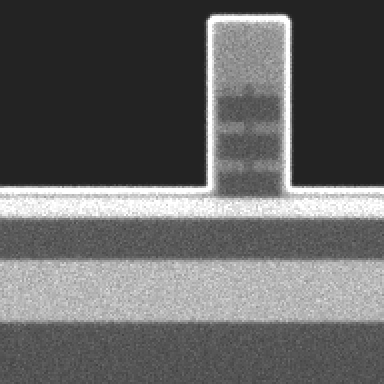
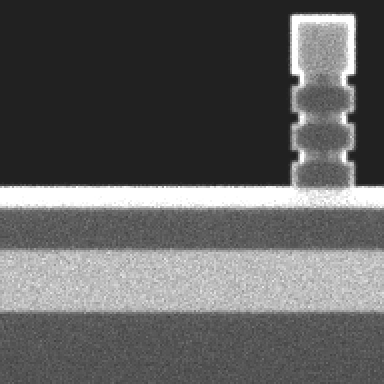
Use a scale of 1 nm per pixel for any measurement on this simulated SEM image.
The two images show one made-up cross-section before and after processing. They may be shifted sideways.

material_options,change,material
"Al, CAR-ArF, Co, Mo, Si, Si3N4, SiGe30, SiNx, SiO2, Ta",removed,SiNx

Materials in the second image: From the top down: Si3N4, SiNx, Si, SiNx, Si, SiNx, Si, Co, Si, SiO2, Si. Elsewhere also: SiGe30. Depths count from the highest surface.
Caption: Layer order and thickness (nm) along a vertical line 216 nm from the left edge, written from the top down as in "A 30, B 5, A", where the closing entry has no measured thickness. empty 172, Co 20, Si 42, SiO2 62, Si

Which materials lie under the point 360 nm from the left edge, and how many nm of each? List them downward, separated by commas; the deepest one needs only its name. empty 172, Co 20, Si 42, SiO2 62, Si